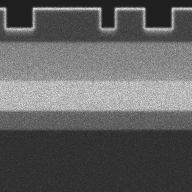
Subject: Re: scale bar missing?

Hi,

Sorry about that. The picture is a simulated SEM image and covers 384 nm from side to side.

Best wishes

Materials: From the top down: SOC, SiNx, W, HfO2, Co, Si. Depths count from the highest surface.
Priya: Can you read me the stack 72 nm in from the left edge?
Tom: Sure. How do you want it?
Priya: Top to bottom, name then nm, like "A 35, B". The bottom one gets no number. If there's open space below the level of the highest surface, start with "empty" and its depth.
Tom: SiNx 68, W 78, HfO2 60, Co 38, Si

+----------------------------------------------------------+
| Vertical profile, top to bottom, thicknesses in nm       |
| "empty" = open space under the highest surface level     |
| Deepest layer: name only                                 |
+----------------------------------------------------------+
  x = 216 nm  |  empty 40, SOC 12, SiNx 16, W 78, HfO2 60, Co 38, Si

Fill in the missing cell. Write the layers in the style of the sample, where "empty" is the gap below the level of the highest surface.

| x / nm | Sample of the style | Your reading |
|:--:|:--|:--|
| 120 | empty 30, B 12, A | SiNx 68, W 78, HfO2 60, Co 38, Si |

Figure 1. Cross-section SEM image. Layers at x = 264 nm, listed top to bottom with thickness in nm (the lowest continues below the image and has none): SiNx 68, W 78, HfO2 60, Co 38, Si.